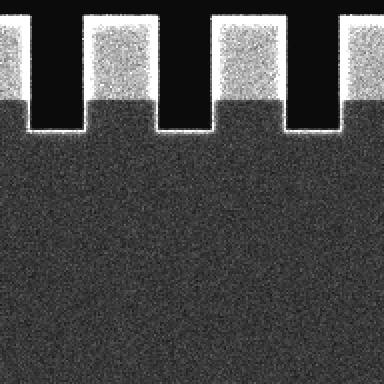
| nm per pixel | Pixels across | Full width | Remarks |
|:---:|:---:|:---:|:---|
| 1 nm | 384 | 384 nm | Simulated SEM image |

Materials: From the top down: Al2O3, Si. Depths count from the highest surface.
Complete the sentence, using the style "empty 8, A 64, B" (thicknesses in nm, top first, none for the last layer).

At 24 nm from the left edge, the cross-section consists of Al2O3 84, Si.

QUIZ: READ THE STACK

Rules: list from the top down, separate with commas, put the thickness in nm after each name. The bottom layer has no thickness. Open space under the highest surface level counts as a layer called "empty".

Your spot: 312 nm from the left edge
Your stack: empty 114, Si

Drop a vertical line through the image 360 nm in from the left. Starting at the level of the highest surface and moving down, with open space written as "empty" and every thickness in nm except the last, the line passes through Al2O3 84, Si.